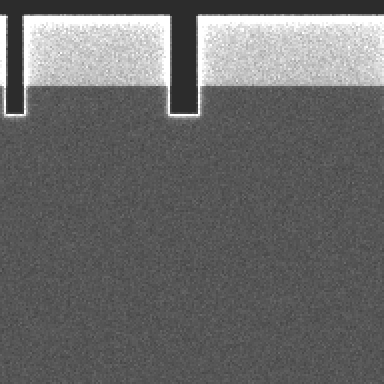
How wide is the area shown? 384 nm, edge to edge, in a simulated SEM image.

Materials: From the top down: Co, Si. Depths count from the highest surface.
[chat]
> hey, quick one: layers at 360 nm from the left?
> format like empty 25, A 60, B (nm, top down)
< Co 70, Si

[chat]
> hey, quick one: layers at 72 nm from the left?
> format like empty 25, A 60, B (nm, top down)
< Co 70, Si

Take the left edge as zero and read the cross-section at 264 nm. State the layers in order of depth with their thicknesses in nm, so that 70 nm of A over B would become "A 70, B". Co 70, Si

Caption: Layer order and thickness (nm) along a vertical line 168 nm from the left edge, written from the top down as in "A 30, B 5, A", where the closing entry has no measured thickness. Co 70, Si